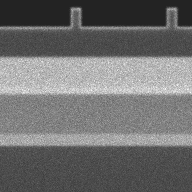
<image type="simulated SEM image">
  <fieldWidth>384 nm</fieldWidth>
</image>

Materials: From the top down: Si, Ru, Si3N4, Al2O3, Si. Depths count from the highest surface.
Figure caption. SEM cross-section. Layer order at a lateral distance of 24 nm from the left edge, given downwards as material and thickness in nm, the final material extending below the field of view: empty 38, Si 60, Ru 74, Si3N4 80, Al2O3 24, Si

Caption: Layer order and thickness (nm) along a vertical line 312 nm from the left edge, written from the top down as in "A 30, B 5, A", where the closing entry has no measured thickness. empty 38, Si 60, Ru 74, Si3N4 80, Al2O3 24, Si